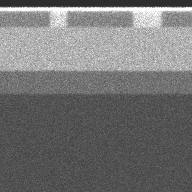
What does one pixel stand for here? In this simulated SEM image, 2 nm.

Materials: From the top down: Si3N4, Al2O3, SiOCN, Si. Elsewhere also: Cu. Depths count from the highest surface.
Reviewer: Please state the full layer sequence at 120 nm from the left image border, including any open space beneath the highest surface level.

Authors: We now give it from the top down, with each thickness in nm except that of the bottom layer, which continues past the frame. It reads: Cu 38, Al2O3 88, SiOCN 46, Si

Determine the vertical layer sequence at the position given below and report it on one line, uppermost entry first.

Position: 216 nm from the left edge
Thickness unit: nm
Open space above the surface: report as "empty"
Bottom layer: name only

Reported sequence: Si3N4 38, Al2O3 88, SiOCN 46, Si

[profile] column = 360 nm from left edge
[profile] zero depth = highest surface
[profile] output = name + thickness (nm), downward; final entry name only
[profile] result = Si3N4 38, Al2O3 88, SiOCN 46, Si